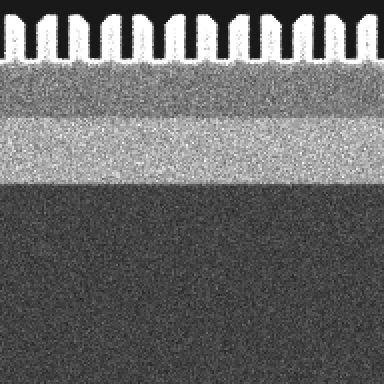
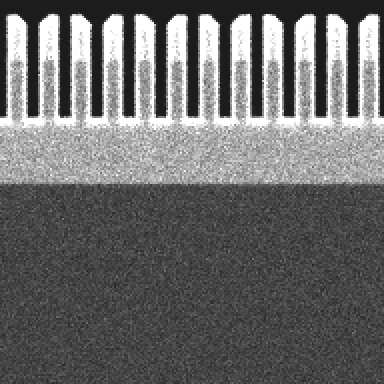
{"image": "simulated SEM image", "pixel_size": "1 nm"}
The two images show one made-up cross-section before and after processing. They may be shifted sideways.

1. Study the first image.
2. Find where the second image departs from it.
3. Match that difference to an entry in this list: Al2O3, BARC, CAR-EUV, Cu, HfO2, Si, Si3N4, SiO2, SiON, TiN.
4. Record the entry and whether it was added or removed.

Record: TiN / removed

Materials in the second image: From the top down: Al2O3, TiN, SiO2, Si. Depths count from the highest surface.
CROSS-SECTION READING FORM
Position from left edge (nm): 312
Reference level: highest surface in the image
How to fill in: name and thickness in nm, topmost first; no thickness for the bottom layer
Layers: Al2O3 44, TiN 58, SiO2 66, Si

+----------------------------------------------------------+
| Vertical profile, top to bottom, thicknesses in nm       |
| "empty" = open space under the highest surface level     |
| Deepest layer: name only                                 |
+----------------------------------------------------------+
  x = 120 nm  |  Al2O3 44, TiN 58, SiO2 66, Si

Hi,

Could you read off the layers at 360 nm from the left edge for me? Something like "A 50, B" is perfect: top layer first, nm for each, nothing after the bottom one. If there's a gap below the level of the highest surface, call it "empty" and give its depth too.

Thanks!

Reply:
empty 8, Al2O3 36, TiN 58, SiO2 66, Si